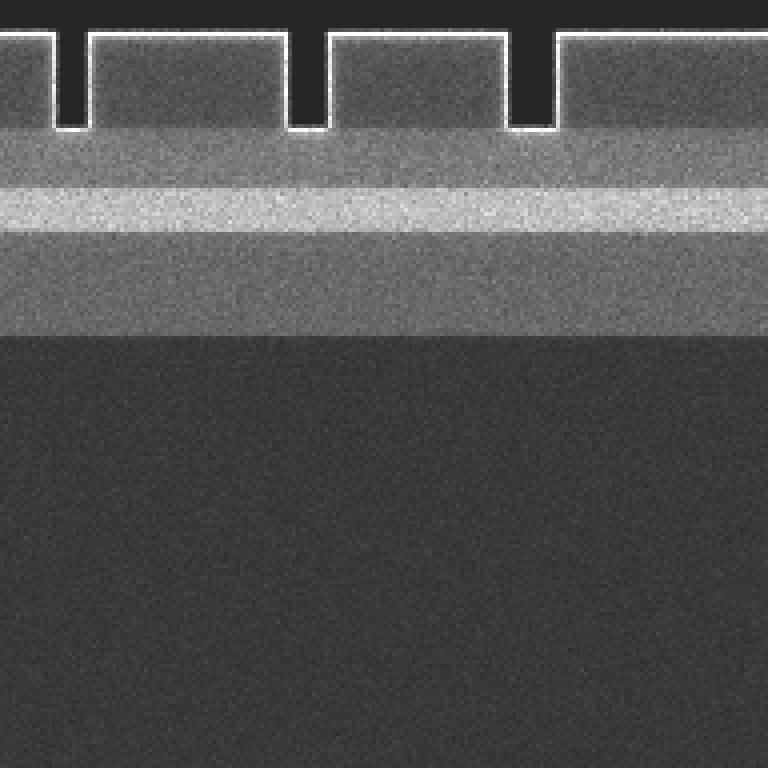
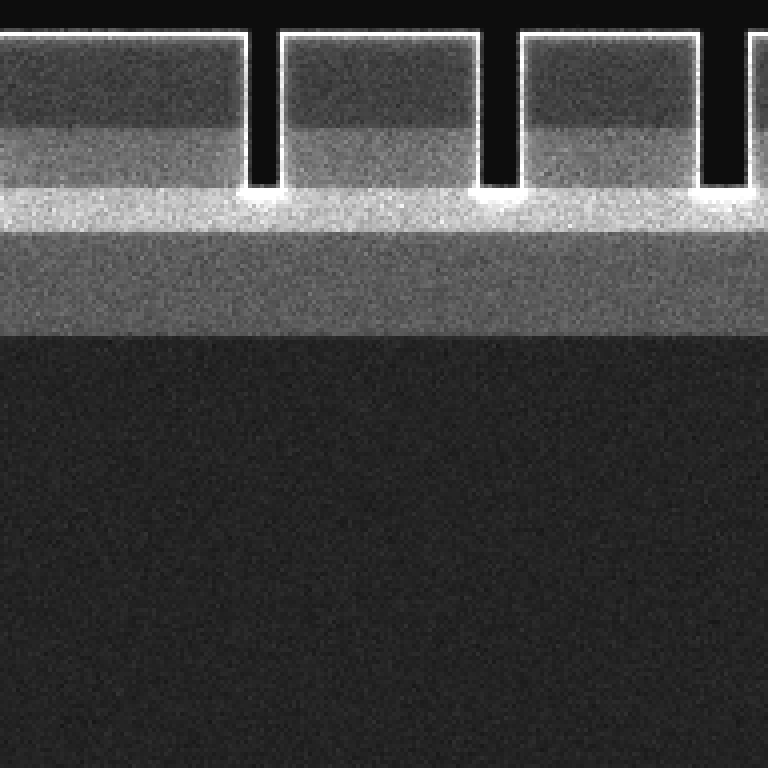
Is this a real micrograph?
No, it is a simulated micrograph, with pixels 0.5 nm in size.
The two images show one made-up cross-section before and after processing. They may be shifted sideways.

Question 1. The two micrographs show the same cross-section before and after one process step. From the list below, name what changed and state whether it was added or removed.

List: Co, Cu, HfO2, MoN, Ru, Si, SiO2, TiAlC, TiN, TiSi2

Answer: Ru, removed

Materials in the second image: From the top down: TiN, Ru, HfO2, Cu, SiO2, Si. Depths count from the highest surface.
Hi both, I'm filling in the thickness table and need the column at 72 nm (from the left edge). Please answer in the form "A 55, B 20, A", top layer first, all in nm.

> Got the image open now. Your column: TiN 48, Ru 30, HfO2 22, Cu 10, SiO2 42, Si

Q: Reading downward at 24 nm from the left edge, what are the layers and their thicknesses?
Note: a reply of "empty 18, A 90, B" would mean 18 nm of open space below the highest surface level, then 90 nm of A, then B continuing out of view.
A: TiN 48, Ru 30, HfO2 22, Cu 10, SiO2 42, Si